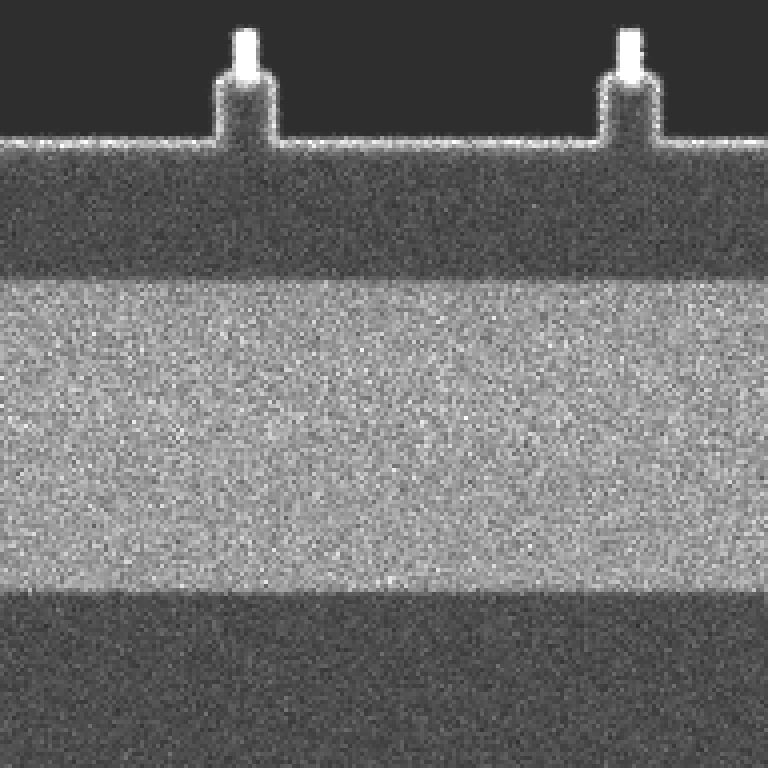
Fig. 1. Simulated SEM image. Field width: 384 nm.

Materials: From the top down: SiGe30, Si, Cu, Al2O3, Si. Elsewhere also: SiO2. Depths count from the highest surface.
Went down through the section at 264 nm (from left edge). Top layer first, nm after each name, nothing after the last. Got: empty 54, SiGe30 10, Si 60, Cu 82, Al2O3 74, Si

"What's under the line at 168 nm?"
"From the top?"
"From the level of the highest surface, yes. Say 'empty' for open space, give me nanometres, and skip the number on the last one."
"empty 54, SiGe30 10, Si 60, Cu 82, Al2O3 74, Si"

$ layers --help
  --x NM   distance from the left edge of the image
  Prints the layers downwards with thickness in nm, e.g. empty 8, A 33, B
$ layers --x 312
SiO2 30, Si 94, Cu 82, Al2O3 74, Si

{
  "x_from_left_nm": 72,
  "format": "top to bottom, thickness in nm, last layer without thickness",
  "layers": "empty 54, SiGe30 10, Si 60, Cu 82, Al2O3 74, Si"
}